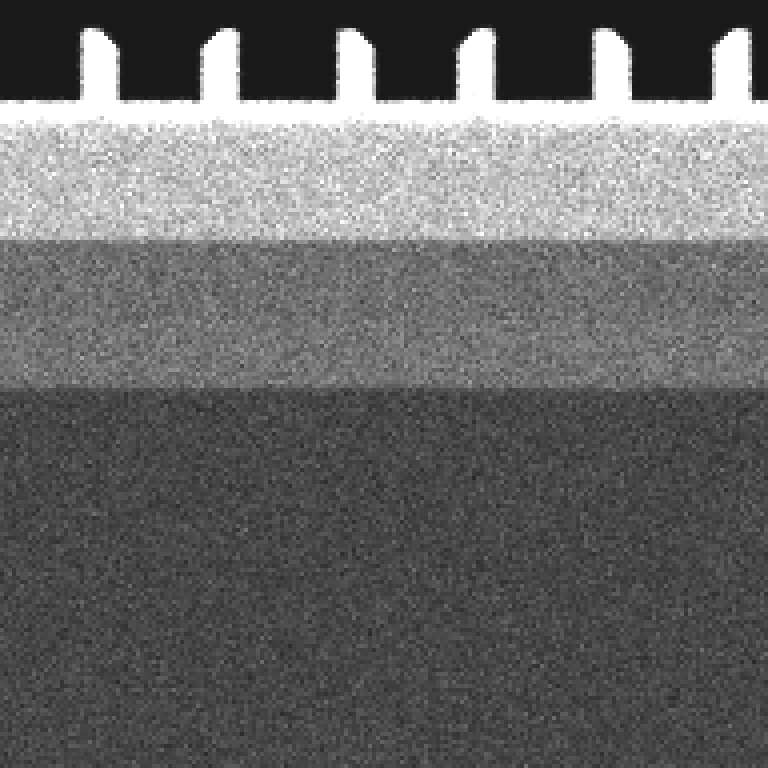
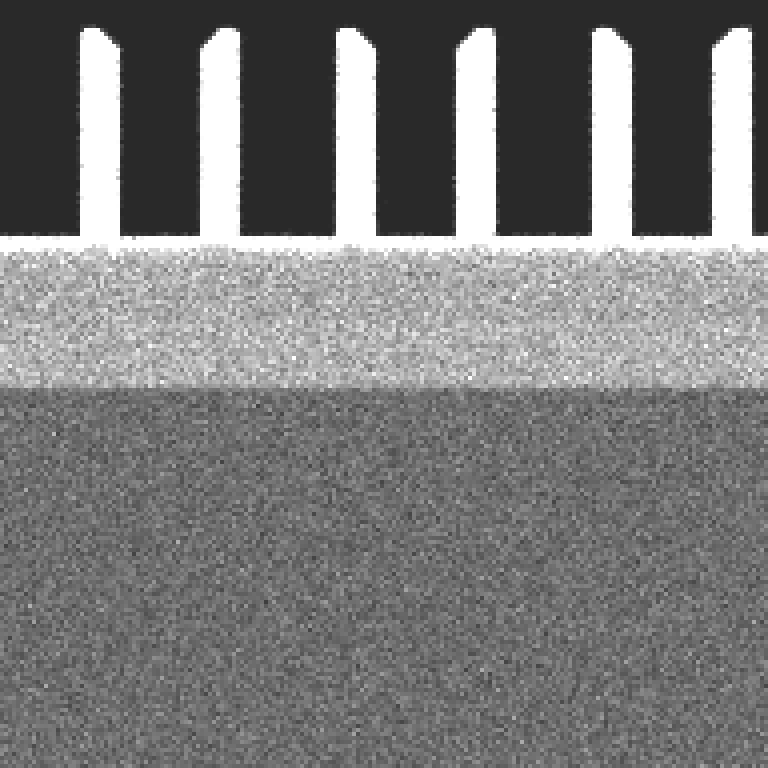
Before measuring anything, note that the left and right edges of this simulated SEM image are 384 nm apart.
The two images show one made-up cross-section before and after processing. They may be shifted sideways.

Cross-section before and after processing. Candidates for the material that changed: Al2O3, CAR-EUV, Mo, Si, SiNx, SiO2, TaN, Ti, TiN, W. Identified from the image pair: Al2O3 (removed).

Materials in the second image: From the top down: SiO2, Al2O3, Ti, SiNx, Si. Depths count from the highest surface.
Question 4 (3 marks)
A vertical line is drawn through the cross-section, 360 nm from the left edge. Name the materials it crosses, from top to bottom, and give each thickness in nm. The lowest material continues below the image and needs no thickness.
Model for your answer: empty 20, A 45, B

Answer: empty 6, SiO2 30, Al2O3 68, Ti 40, SiNx 34, Si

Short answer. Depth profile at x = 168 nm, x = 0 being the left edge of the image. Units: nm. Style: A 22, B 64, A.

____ empty 104, Ti 40, SiNx 34, Si